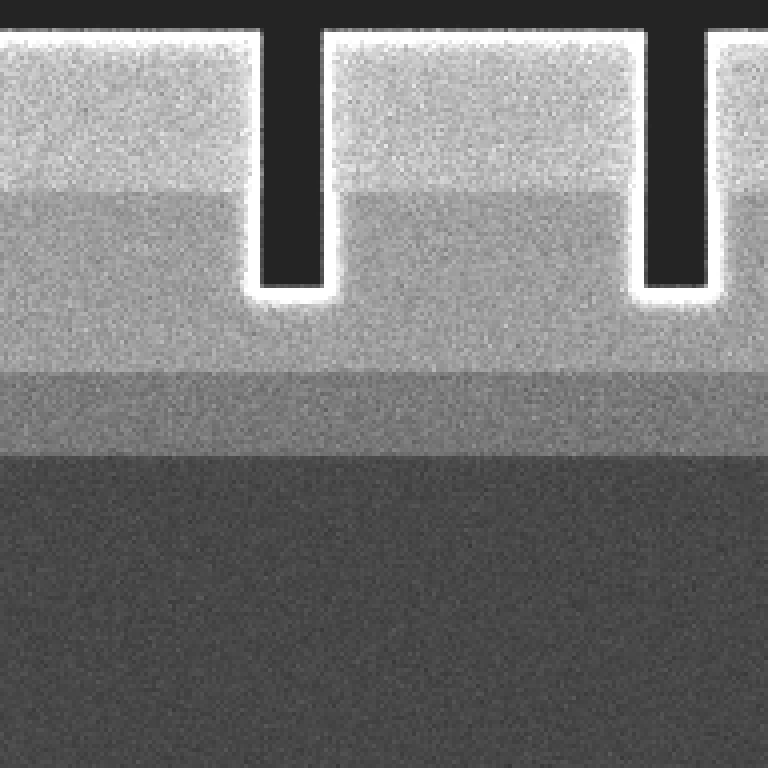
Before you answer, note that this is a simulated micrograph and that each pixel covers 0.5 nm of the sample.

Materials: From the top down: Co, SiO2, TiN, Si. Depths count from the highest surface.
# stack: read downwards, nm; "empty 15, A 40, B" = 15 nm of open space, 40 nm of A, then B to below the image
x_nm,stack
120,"Co 80, SiO2 90, TiN 42, Si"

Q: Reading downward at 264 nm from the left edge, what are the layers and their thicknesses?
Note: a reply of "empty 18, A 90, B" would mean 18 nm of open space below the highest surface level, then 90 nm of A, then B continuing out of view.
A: Co 80, SiO2 90, TiN 42, Si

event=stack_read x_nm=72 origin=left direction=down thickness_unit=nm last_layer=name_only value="Co 80, SiO2 90, TiN 42, Si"